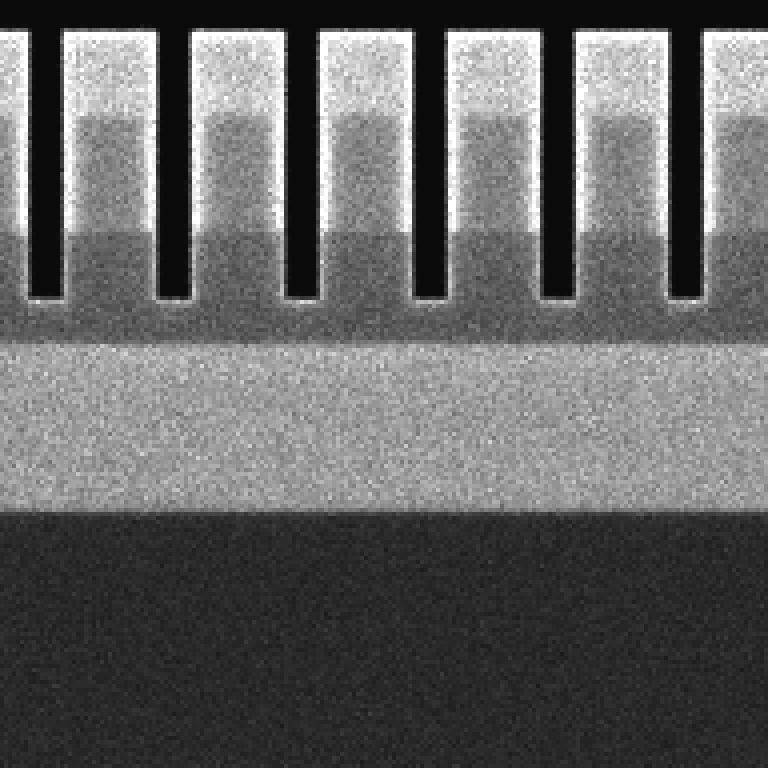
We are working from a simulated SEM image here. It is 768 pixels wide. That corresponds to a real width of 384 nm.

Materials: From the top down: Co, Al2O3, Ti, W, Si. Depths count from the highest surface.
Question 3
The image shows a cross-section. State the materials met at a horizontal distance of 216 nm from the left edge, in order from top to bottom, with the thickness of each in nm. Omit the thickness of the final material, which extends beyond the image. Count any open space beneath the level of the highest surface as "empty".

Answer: empty 134, Ti 22, W 84, Si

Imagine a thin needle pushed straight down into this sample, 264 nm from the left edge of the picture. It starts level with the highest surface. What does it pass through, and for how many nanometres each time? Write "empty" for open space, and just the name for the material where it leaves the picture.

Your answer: Co 42, Al2O3 58, Ti 56, W 84, Si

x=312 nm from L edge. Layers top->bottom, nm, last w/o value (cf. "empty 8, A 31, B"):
Co 42, Al2O3 58, Ti 56, W 84, Si